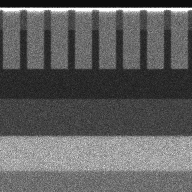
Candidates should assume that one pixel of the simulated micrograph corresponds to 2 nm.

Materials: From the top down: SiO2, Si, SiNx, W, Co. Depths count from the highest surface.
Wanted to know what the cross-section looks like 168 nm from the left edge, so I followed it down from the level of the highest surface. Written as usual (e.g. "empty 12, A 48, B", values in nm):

SiO2 122, Si 60, SiNx 74, W 70, Co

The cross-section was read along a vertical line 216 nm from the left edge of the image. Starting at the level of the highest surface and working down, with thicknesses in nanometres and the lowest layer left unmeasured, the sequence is SiO2 122, Si 60, SiNx 74, W 70, Co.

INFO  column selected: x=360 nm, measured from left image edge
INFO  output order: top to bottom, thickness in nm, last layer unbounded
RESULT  SiO2 122, Si 60, SiNx 74, W 70, Co